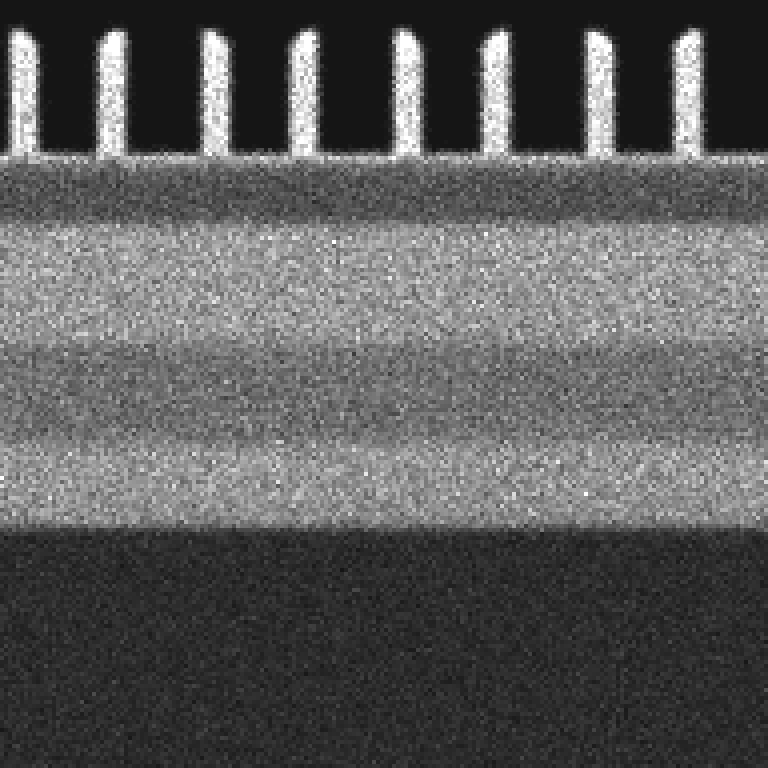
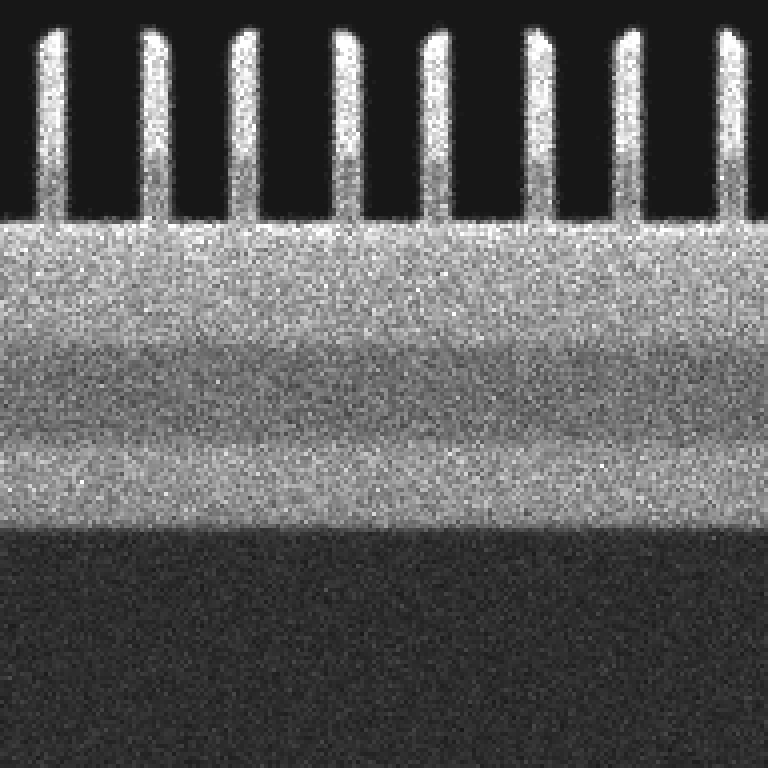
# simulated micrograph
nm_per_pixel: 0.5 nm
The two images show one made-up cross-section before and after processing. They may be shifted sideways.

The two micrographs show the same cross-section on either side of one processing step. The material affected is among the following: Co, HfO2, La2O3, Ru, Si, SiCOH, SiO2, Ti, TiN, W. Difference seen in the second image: TiN removed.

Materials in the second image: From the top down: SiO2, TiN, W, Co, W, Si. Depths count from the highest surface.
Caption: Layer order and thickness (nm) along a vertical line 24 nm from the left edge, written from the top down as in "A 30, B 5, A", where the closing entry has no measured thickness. empty 2, SiO2 60, TiN 34, W 60, Co 50, W 42, Si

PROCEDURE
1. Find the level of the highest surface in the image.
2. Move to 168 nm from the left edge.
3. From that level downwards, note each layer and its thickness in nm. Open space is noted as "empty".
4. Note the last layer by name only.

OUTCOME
SiO2 62, TiN 34, W 60, Co 50, W 42, Si